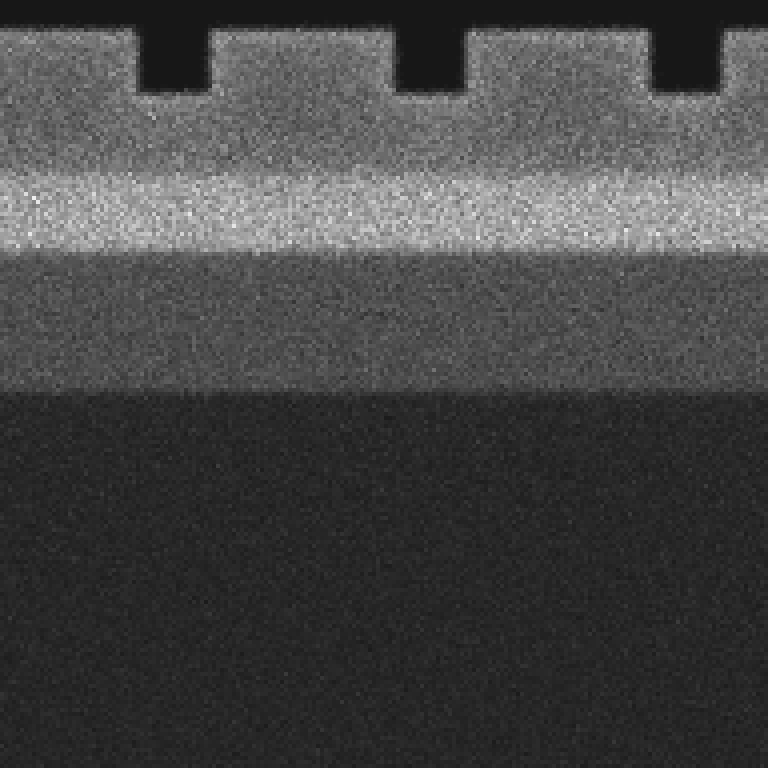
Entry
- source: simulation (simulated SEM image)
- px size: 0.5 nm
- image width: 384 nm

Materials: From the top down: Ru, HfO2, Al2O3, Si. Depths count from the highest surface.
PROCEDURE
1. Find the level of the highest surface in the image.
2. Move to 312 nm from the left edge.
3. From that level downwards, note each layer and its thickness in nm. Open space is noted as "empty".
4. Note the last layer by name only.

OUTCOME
Ru 72, HfO2 38, Al2O3 70, Si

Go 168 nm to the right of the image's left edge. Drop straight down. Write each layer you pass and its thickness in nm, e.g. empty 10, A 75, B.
Ru 72, HfO2 38, Al2O3 70, Si